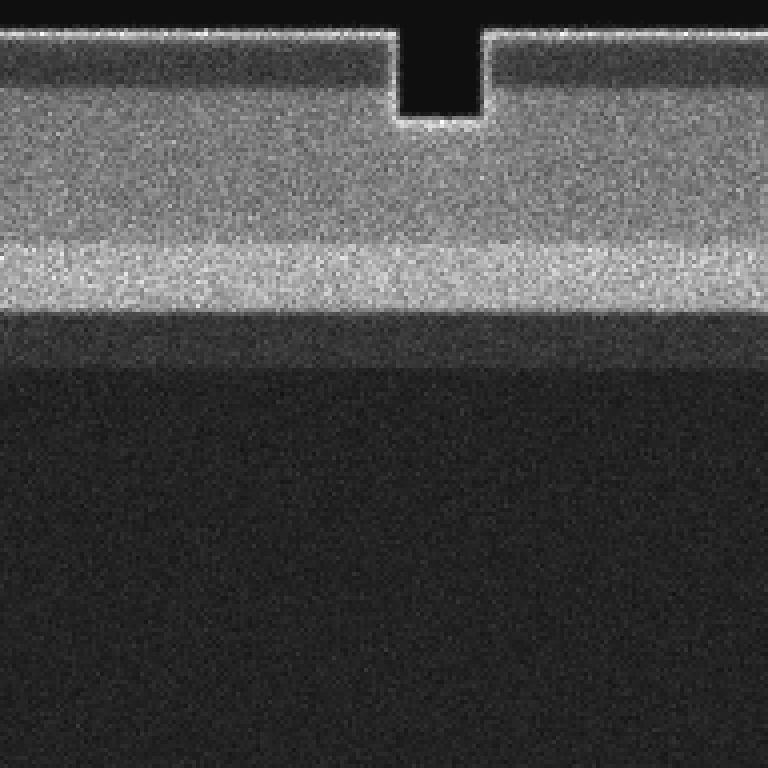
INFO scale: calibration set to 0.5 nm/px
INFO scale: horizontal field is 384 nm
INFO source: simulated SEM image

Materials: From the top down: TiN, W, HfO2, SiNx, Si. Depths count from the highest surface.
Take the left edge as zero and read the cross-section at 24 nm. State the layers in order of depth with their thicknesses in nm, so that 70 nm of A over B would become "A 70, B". TiN 28, W 78, HfO2 34, SiNx 28, Si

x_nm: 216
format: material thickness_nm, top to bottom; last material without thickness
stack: empty 44, W 62, HfO2 34, SiNx 28, Si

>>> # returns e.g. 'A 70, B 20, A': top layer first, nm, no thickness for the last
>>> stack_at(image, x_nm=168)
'TiN 28, W 78, HfO2 34, SiNx 28, Si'